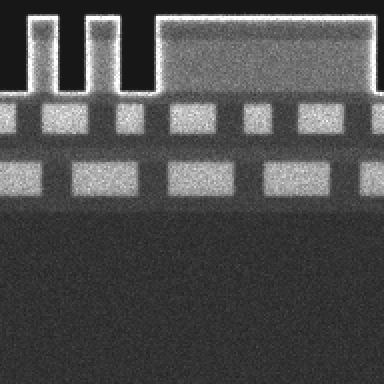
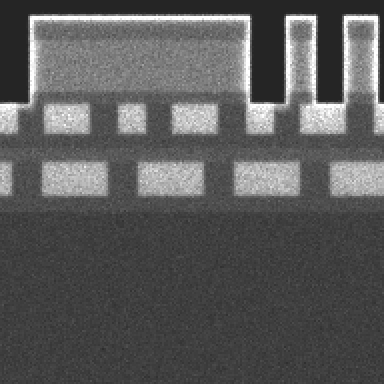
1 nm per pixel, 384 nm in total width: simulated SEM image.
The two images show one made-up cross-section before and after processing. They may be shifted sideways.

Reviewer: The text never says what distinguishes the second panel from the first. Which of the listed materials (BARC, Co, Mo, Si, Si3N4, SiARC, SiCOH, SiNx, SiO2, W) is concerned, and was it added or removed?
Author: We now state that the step removed SiNx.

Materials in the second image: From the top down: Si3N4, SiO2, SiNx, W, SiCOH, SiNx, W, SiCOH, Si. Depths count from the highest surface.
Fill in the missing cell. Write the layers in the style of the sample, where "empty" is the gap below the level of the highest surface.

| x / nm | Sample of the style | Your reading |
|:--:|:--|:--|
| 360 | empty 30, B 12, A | Si3N4 24, SiO2 52, SiNx 12, SiCOH 44, SiNx 14, W 34, SiCOH 16, Si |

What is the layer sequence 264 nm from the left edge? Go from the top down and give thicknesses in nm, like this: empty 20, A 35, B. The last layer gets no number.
empty 88, W 30, SiCOH 14, SiNx 14, W 34, SiCOH 16, Si